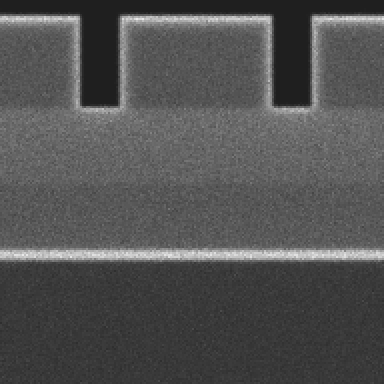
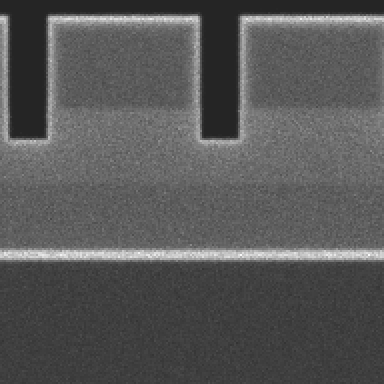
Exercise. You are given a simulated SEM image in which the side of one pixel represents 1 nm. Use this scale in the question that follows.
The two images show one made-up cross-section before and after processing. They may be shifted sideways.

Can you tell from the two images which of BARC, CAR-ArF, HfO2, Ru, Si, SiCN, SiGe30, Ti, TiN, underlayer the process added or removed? Yes, it removed TiN.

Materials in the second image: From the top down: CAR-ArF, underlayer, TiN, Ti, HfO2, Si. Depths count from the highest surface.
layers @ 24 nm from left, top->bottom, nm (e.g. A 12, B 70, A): empty 124, TiN 44, Ti 66, HfO2 10, Si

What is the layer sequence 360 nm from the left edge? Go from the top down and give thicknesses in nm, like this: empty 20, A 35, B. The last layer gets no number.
CAR-ArF 50, underlayer 42, TiN 76, Ti 66, HfO2 10, Si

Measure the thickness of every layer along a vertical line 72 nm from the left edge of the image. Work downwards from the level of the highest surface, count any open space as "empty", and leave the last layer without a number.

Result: CAR-ArF 50, underlayer 42, TiN 76, Ti 66, HfO2 10, Si